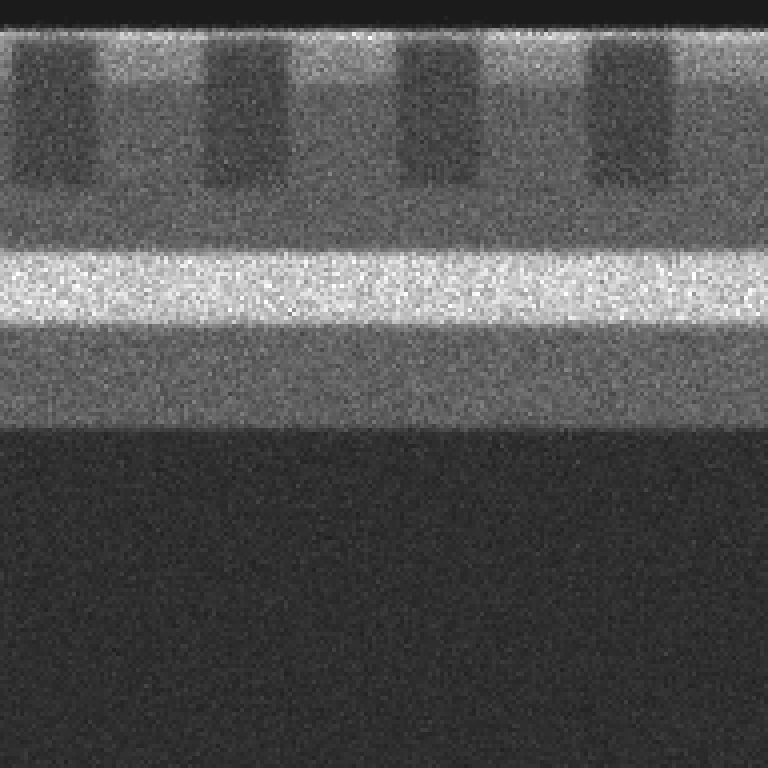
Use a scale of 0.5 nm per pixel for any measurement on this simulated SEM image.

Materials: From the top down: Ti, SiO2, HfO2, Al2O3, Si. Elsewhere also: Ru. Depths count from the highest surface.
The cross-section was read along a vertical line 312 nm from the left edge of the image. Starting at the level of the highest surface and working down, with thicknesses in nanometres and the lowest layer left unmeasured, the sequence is Ti 78, SiO2 32, HfO2 36, Al2O3 52, Si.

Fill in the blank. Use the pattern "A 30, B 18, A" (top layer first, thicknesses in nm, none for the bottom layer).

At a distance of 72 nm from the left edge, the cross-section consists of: Ru 26, SiO2 84, HfO2 36, Al2O3 52, Si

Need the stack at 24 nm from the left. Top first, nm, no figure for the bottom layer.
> Ti 78, SiO2 32, HfO2 36, Al2O3 52, Si